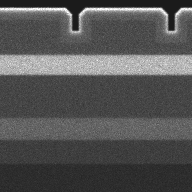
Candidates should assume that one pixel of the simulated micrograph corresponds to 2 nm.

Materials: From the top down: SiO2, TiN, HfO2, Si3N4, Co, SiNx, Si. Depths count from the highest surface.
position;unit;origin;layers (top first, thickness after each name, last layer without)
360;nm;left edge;empty 2, SiO2 68, TiN 24, HfO2 40, Si3N4 86, Co 44, SiNx 48, Si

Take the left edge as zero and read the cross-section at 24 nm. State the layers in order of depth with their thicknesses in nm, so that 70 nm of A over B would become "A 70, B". SiO2 24, TiN 70, HfO2 40, Si3N4 86, Co 44, SiNx 48, Si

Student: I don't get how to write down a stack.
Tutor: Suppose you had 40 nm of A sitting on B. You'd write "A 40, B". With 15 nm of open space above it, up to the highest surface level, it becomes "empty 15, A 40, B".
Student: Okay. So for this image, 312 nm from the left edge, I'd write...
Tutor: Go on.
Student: SiO2 70, TiN 24, HfO2 40, Si3N4 86, Co 44, SiNx 48, Si